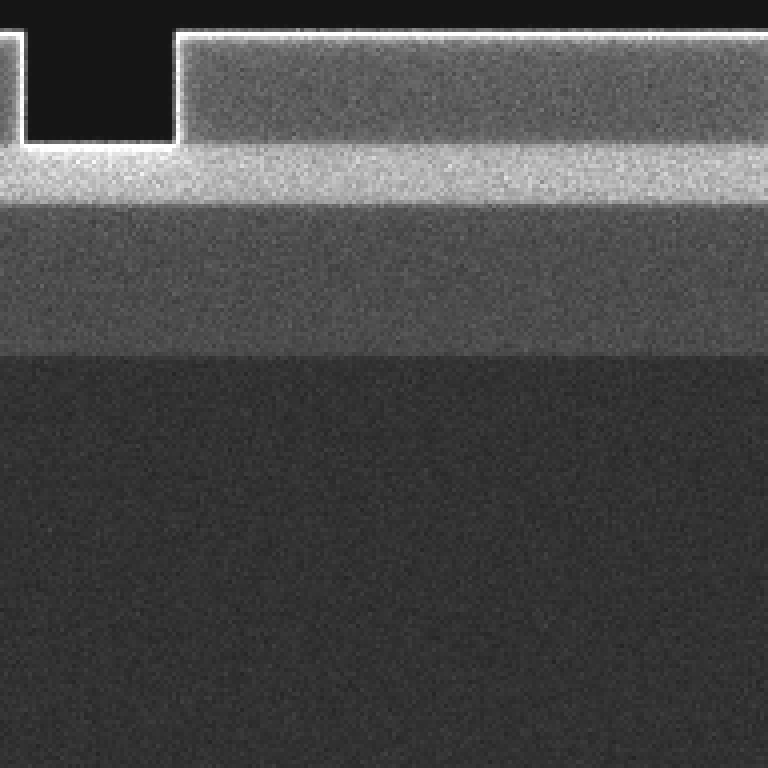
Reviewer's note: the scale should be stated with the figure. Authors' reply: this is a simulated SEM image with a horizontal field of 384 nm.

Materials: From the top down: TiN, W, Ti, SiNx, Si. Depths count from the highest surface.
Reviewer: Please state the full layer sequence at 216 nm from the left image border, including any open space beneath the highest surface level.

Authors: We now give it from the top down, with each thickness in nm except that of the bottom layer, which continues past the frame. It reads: TiN 56, W 30, Ti 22, SiNx 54, Si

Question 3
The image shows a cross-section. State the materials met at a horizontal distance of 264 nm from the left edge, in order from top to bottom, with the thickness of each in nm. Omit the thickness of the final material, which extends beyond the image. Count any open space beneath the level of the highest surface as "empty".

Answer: TiN 56, W 30, Ti 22, SiNx 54, Si